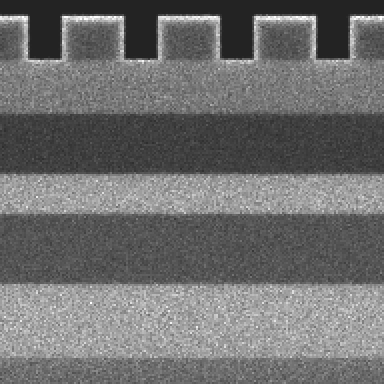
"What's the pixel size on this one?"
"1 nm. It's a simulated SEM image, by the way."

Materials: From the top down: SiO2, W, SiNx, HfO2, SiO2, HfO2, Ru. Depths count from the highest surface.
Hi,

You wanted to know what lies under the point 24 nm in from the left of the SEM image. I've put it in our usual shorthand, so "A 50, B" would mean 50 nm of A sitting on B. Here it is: SiO2 44, W 54, SiNx 60, HfO2 40, SiO2 70, HfO2 74, Ru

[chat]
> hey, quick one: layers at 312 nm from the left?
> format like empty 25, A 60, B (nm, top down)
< SiO2 44, W 54, SiNx 60, HfO2 40, SiO2 70, HfO2 74, Ru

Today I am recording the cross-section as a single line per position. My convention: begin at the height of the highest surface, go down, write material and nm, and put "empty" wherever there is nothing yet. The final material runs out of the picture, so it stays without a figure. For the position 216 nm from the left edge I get SiO2 44, W 54, SiNx 60, HfO2 40, SiO2 70, HfO2 74, Ru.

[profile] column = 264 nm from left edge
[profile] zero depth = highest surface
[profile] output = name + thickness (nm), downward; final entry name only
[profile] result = SiO2 44, W 54, SiNx 60, HfO2 40, SiO2 70, HfO2 74, Ru